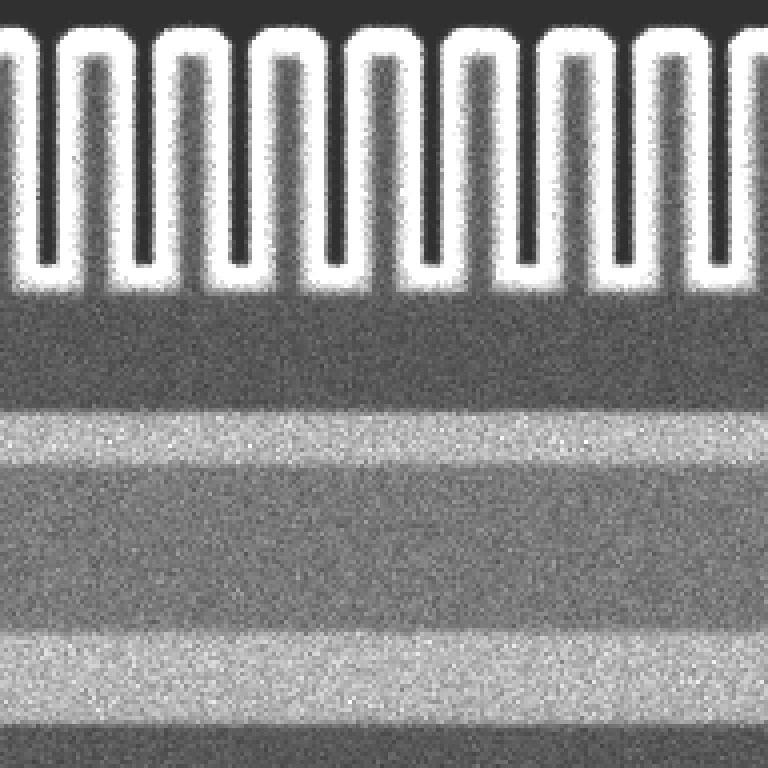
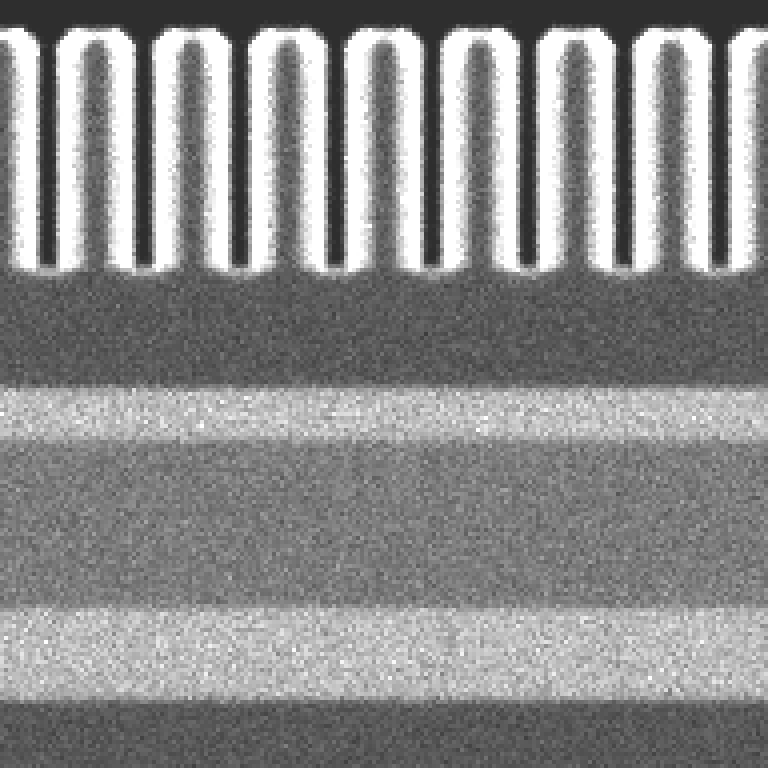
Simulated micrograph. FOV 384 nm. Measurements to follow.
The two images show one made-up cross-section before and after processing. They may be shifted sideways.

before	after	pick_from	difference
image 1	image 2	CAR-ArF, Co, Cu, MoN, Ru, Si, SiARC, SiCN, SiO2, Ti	SiO2 removed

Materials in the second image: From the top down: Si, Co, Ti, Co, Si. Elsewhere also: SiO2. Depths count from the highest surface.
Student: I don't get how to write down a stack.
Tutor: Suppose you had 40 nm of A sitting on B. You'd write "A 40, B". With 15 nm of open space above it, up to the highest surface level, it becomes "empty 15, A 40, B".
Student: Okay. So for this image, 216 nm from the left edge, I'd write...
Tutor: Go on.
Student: empty 118, Si 60, Co 26, Ti 84, Co 46, Si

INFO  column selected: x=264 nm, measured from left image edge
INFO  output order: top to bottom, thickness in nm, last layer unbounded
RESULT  empty 118, Si 60, Co 26, Ti 84, Co 46, Si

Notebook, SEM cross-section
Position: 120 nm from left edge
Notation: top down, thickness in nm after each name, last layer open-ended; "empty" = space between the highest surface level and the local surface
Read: empty 118, Si 60, Co 26, Ti 84, Co 46, Si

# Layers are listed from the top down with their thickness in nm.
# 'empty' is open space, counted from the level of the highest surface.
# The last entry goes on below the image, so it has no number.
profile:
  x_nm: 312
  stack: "empty 118, Si 60, Co 26, Ti 84, Co 46, Si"